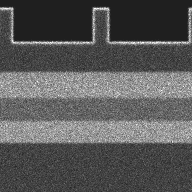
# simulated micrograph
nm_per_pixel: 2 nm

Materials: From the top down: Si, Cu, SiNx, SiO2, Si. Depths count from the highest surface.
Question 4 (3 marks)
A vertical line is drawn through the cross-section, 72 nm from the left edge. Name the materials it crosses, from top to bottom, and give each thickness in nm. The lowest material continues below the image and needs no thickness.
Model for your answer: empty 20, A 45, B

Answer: empty 68, Si 60, Cu 52, SiNx 46, SiO2 44, Si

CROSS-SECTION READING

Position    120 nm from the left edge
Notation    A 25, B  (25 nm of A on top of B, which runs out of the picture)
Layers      empty 68, Si 60, Cu 52, SiNx 46, SiO2 44, Si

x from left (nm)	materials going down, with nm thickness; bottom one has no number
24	Si 128, Cu 52, SiNx 46, SiO2 44, Si